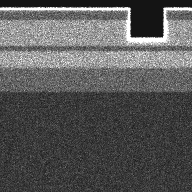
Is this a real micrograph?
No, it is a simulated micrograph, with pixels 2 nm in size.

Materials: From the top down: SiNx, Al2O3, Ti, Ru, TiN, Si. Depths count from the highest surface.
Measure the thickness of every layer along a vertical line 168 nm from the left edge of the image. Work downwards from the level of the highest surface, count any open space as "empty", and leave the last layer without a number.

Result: SiNx 24, Al2O3 52, Ti 10, Ru 34, TiN 48, Si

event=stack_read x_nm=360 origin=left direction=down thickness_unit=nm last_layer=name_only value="SiNx 24, Al2O3 52, Ti 10, Ru 34, TiN 48, Si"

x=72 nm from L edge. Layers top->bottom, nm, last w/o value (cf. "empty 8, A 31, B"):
SiNx 24, Al2O3 52, Ti 10, Ru 34, TiN 48, Si